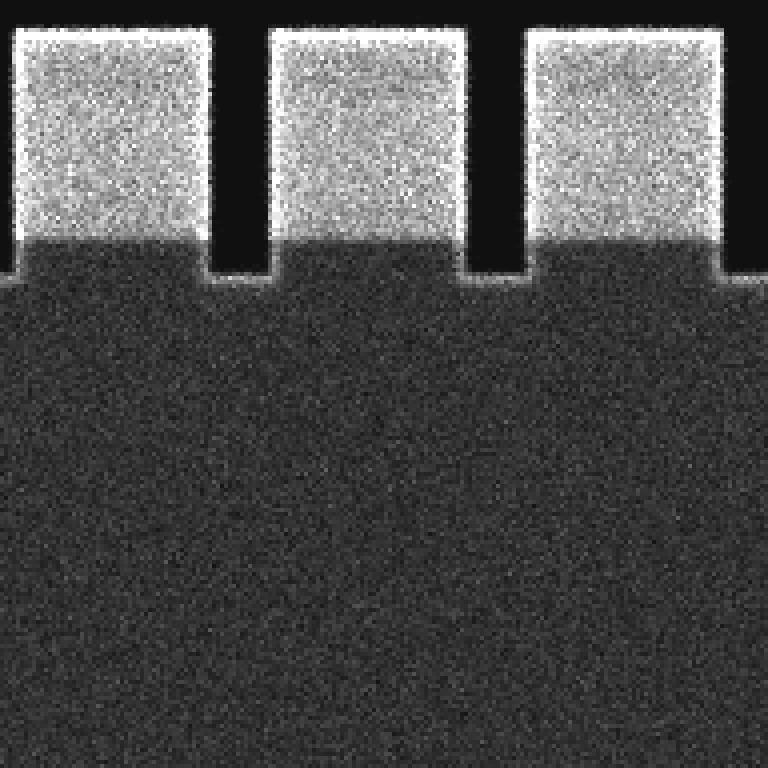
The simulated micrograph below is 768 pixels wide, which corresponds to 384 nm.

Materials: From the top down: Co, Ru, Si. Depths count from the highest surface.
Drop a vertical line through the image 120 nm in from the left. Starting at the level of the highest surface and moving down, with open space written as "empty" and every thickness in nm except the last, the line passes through empty 122, Si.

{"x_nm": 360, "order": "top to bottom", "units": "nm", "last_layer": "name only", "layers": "empty 122, Si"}